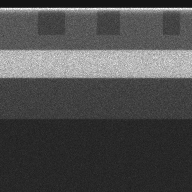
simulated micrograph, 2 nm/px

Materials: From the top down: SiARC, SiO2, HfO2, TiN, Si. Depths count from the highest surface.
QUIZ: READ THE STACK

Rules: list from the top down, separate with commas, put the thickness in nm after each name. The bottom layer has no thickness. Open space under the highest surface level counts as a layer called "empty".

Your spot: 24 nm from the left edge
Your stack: SiARC 6, SiO2 78, HfO2 56, TiN 82, Si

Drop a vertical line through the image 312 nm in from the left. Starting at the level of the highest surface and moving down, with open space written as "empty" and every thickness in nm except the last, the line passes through SiARC 6, SiO2 78, HfO2 56, TiN 82, Si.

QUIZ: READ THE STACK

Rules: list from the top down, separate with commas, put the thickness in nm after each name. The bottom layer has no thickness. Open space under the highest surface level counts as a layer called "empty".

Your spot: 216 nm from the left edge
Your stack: SiARC 54, SiO2 30, HfO2 56, TiN 82, Si